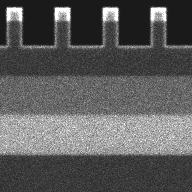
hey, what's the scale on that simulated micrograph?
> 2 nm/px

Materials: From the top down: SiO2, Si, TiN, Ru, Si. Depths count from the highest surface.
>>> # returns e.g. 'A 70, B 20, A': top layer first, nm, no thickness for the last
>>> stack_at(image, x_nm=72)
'empty 76, Si 60, TiN 78, Ru 80, Si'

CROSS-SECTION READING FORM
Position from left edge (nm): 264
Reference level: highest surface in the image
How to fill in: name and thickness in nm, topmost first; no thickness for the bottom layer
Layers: empty 76, Si 60, TiN 78, Ru 80, Si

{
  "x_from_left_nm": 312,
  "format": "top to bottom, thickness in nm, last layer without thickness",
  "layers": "SiO2 26, Si 110, TiN 78, Ru 80, Si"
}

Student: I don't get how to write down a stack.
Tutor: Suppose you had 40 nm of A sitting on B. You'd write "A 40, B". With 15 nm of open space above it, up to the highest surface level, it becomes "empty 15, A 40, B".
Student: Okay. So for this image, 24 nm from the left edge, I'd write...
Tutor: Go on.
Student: SiO2 26, Si 110, TiN 78, Ru 80, Si